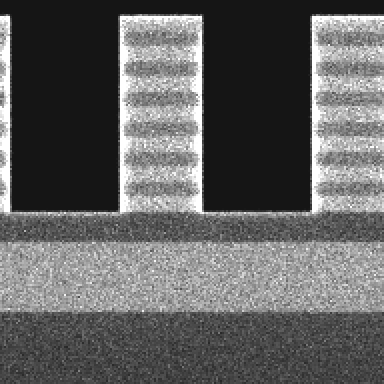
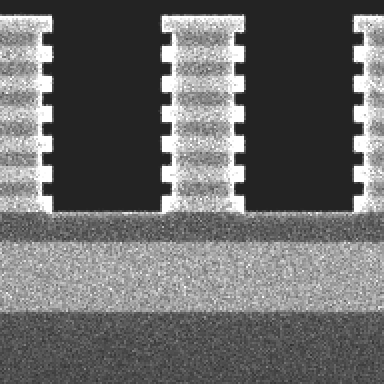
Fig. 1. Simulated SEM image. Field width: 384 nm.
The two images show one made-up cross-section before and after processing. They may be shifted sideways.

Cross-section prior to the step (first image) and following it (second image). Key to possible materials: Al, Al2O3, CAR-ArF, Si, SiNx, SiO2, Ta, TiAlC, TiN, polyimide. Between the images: SiNx was removed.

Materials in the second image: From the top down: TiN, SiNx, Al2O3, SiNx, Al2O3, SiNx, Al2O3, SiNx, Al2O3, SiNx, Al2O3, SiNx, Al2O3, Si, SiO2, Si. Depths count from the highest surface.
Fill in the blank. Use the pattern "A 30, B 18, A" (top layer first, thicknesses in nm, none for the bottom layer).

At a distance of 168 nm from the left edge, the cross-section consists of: TiN 16, empty 14, Al2O3 16, empty 14, Al2O3 16, empty 14, Al2O3 16, empty 14, Al2O3 16, empty 14, Al2O3 16, empty 14, Al2O3 16, Si 30, SiO2 70, Si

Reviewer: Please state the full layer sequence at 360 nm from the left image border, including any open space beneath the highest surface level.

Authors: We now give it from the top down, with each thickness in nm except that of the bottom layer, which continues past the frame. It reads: TiN 16, empty 14, Al2O3 16, empty 14, Al2O3 16, empty 14, Al2O3 16, empty 14, Al2O3 16, empty 14, Al2O3 16, empty 14, Al2O3 16, Si 30, SiO2 70, Si